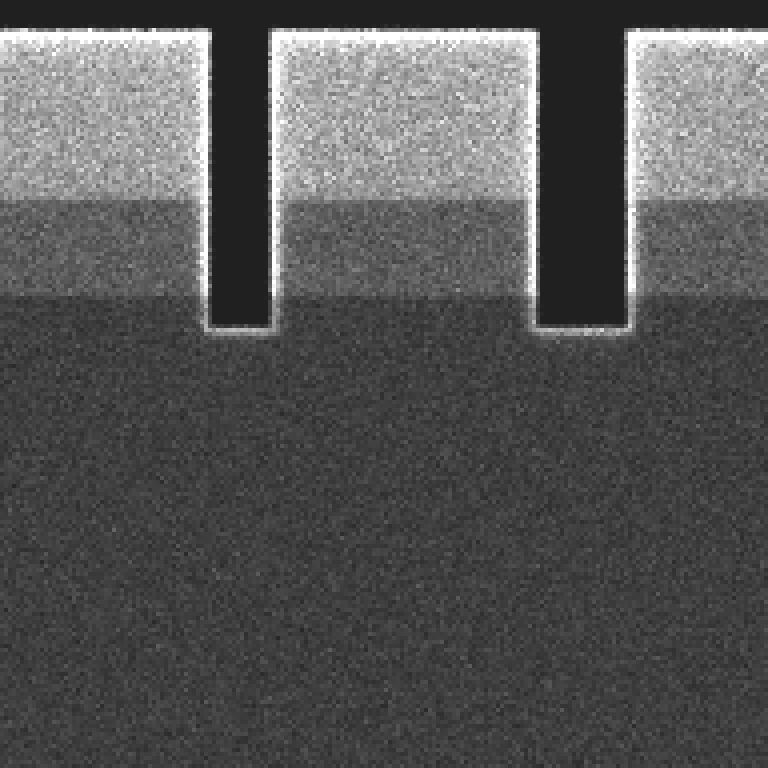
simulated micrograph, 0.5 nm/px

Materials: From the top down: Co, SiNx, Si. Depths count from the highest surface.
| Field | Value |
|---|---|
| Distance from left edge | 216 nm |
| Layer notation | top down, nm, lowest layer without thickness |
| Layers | Co 84, SiNx 48, Si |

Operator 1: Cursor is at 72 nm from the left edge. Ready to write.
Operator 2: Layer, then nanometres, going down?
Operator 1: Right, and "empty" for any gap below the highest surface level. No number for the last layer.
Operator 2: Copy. Co 84, SiNx 48, Si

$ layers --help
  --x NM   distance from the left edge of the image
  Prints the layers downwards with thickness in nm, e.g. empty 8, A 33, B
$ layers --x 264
Co 84, SiNx 48, Si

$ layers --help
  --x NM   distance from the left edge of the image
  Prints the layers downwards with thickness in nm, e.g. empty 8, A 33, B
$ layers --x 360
Co 84, SiNx 48, Si